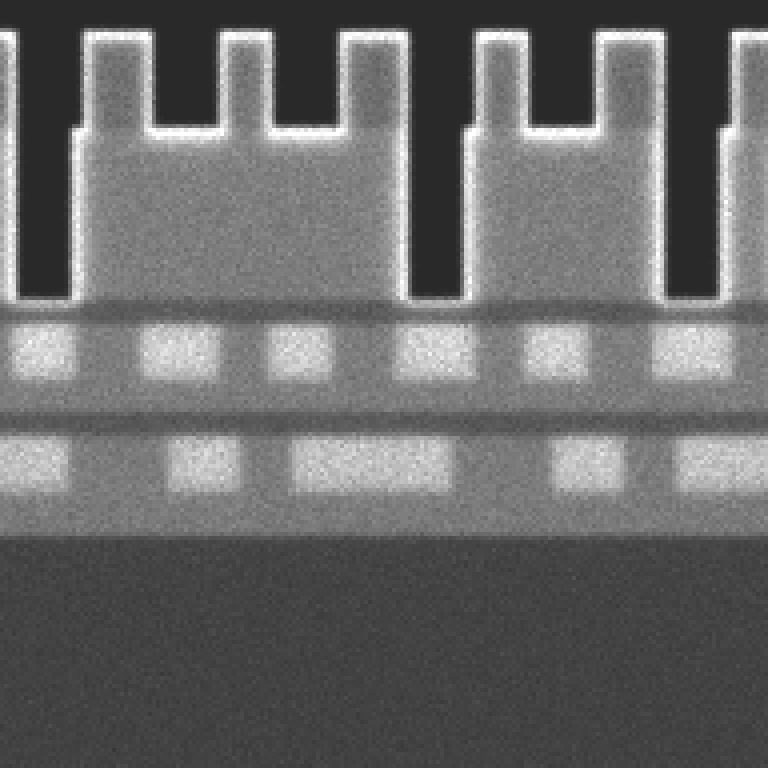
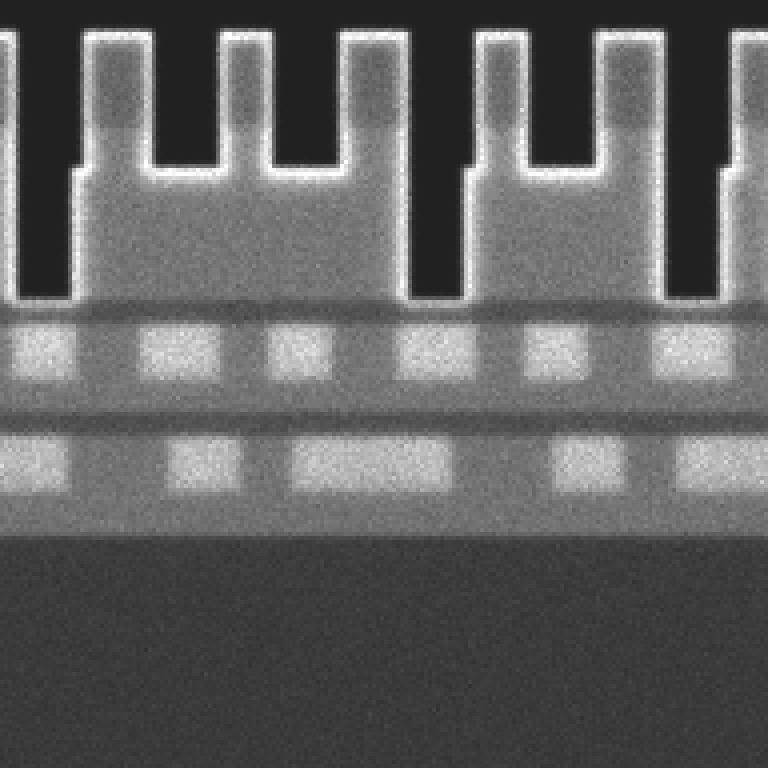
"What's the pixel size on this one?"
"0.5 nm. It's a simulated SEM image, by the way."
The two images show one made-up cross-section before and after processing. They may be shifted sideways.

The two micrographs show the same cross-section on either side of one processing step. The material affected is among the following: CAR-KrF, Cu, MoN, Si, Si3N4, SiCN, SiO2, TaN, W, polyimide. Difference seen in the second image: SiO2 removed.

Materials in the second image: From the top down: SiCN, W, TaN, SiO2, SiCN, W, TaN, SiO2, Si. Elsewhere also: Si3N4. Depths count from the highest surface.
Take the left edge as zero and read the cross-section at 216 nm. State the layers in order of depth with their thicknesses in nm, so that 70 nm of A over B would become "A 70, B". empty 134, SiCN 12, W 22, TaN 6, SiO2 16, SiCN 12, W 22, TaN 6, SiO2 22, Si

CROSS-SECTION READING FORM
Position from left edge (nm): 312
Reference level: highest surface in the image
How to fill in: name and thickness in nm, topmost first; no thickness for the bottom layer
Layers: Si3N4 48, SiO2 86, SiCN 12, SiO2 44, SiCN 12, SiO2 50, Si